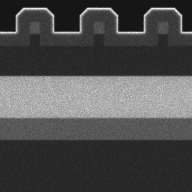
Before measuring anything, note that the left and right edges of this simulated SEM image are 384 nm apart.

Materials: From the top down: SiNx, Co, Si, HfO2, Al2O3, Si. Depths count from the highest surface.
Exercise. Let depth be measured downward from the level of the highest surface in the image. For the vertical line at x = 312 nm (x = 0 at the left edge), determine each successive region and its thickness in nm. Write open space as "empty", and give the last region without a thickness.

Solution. SiNx 76, Si 60, HfO2 84, Al2O3 44, Si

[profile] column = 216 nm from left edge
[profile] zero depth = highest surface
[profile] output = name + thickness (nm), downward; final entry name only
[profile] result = SiNx 76, Si 60, HfO2 84, Al2O3 44, Si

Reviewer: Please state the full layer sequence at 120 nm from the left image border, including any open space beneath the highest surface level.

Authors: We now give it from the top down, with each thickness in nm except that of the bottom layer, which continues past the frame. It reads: empty 48, SiNx 28, Si 60, HfO2 84, Al2O3 44, Si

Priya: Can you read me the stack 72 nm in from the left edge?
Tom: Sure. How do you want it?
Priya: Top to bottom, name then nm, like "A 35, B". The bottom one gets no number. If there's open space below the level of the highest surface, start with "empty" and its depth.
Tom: SiNx 28, Co 24, Si 84, HfO2 84, Al2O3 44, Si